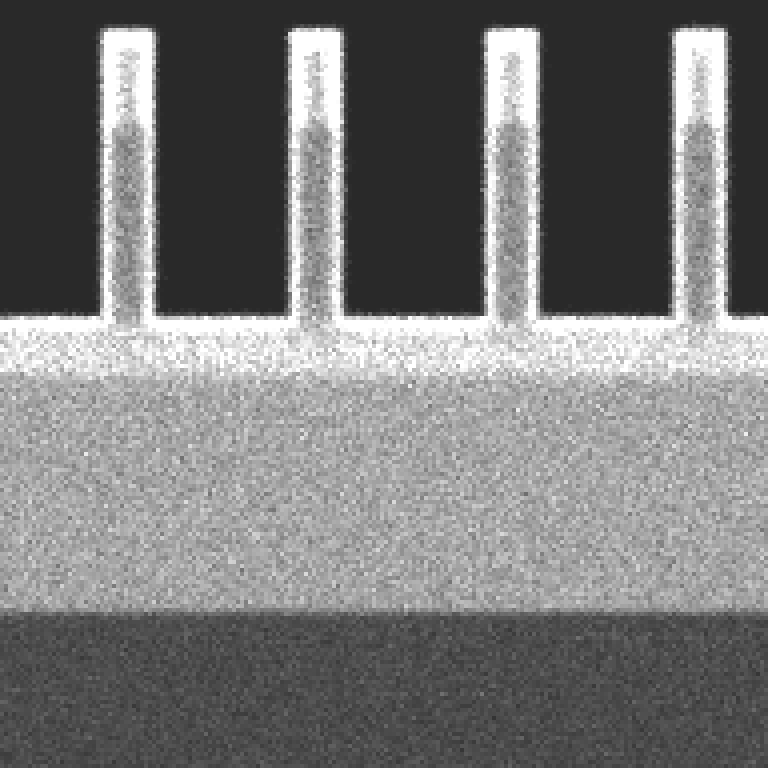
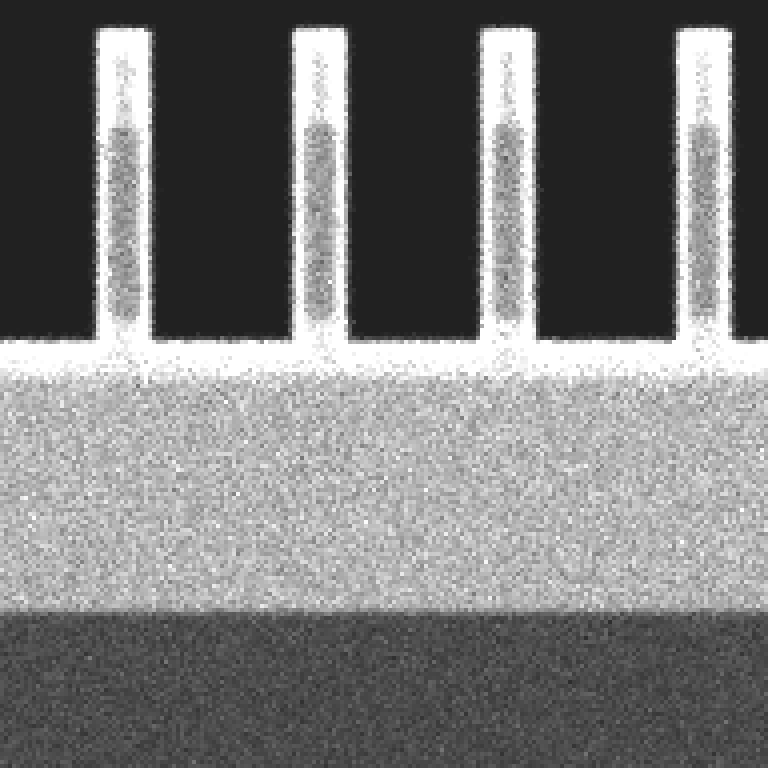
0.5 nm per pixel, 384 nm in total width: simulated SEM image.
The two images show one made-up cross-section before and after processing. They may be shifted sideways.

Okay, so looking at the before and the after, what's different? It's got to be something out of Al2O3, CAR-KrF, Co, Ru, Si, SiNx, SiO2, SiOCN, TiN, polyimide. Co, removed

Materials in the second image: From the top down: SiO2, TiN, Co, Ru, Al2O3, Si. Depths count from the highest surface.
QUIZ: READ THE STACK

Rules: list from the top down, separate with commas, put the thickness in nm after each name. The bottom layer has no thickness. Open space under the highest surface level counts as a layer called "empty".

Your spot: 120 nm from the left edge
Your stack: empty 156, Ru 16, Al2O3 118, Si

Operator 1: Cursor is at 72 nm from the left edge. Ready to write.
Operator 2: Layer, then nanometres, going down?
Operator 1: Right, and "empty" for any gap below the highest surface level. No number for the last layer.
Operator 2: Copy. SiO2 46, TiN 98, Co 12, Ru 16, Al2O3 118, Si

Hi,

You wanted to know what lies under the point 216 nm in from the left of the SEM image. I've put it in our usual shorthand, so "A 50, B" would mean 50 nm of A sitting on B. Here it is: empty 156, Ru 16, Al2O3 118, Si